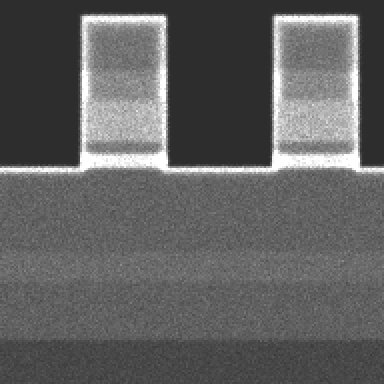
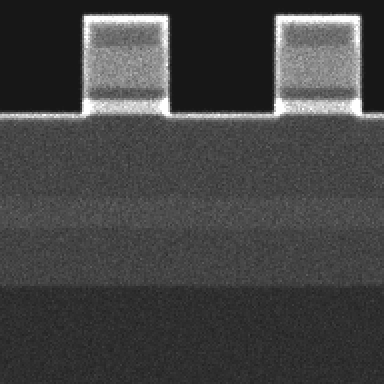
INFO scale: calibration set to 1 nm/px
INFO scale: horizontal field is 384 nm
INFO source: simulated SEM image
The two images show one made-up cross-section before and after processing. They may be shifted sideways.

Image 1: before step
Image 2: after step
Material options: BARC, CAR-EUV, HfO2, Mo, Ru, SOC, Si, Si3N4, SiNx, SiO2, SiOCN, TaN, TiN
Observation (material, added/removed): SOC, removed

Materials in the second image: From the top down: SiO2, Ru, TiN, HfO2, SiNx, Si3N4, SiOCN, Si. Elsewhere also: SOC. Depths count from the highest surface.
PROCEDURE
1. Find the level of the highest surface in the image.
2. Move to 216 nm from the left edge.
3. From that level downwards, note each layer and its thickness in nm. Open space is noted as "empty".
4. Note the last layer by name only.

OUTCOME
empty 98, SiNx 84, Si3N4 30, SiOCN 58, Si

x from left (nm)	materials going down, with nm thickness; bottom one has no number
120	SiO2 30, Ru 42, TiN 12, HfO2 14, SiNx 84, Si3N4 30, SiOCN 58, Si